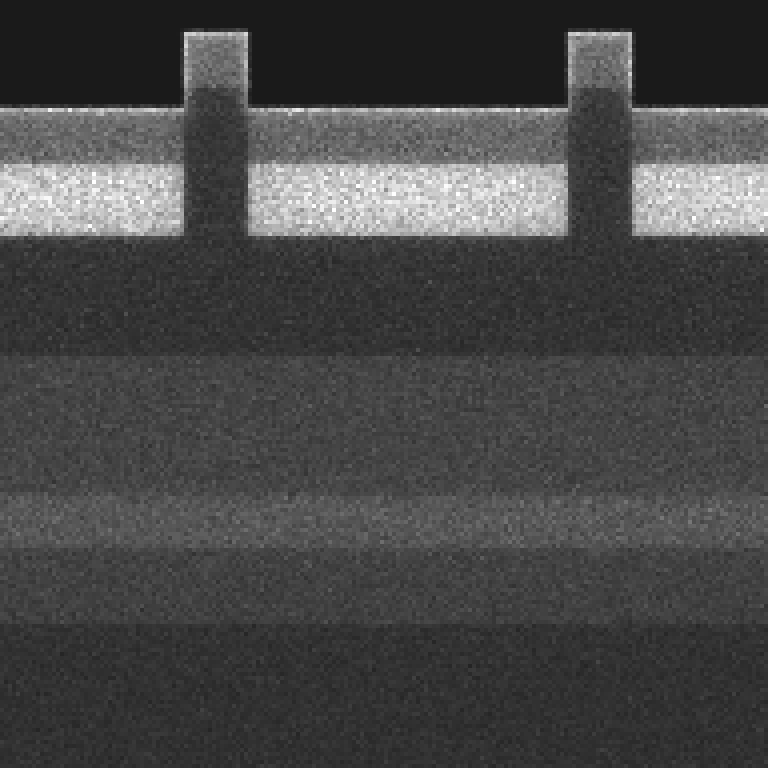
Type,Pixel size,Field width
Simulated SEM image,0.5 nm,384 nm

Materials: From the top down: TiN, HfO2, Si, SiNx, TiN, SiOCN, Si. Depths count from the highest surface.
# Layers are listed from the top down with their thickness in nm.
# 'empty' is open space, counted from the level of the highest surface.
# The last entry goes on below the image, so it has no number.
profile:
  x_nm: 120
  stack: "TiN 28, Si 134, SiNx 70, TiN 26, SiOCN 38, Si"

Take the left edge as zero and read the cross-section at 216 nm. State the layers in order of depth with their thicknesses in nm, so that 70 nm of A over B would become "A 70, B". empty 38, TiN 28, HfO2 36, Si 60, SiNx 70, TiN 26, SiOCN 38, Si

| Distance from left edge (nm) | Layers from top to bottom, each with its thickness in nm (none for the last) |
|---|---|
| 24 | empty 38, TiN 28, HfO2 36, Si 60, SiNx 70, TiN 26, SiOCN 38, Si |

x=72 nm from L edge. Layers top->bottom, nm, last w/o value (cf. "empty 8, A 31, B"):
empty 38, TiN 28, HfO2 36, Si 60, SiNx 70, TiN 26, SiOCN 38, Si